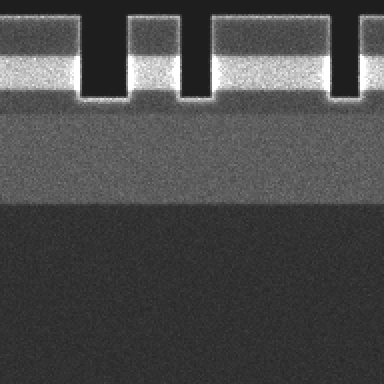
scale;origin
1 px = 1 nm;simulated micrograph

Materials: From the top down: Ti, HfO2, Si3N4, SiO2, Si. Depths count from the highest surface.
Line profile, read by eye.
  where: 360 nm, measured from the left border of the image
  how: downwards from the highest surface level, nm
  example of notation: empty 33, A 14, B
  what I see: Ti 40, HfO2 34, Si3N4 24, SiO2 90, Si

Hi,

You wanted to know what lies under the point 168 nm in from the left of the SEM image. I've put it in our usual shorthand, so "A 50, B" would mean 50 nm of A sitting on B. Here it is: Ti 40, HfO2 34, Si3N4 24, SiO2 90, Si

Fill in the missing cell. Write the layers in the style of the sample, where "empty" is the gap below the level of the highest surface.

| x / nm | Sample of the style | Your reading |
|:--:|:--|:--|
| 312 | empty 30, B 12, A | Ti 40, HfO2 34, Si3N4 24, SiO2 90, Si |